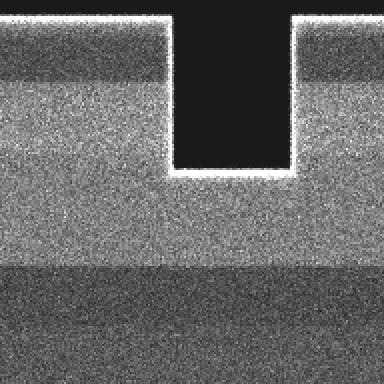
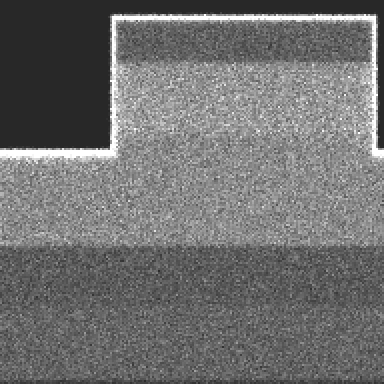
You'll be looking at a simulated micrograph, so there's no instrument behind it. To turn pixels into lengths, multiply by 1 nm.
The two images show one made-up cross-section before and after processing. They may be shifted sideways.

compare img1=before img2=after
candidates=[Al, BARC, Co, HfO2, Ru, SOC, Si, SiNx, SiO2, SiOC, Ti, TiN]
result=removed:SOC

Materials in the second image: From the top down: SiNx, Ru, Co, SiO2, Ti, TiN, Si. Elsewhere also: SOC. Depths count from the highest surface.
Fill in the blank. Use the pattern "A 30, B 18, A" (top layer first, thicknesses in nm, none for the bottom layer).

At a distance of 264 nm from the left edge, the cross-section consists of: SiNx 46, Ru 72, Co 16, SiO2 96, Ti 60, TiN 74, Si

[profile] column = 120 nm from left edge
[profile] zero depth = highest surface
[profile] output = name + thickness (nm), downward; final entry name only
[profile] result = SiNx 46, Ru 72, Co 16, SiO2 96, Ti 60, TiN 74, Si